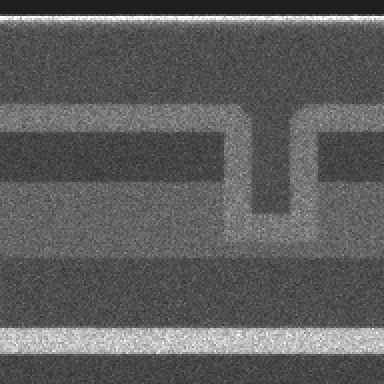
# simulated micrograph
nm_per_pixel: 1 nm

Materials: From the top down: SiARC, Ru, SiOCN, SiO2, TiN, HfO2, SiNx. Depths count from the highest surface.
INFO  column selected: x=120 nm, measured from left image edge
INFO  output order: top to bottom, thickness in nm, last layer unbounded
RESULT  SiARC 88, Ru 28, SiOCN 50, SiO2 76, TiN 70, HfO2 26, SiNx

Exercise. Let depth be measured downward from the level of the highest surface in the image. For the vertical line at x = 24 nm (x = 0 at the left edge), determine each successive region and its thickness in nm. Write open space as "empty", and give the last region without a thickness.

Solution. SiARC 88, Ru 28, SiOCN 50, SiO2 76, TiN 70, HfO2 26, SiNx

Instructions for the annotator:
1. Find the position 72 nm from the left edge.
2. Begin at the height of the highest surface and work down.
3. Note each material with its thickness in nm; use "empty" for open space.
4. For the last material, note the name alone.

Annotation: SiARC 88, Ru 28, SiOCN 50, SiO2 76, TiN 70, HfO2 26, SiNx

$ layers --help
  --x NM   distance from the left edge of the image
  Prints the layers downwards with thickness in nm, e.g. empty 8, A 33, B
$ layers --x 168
SiARC 88, Ru 28, SiOCN 50, SiO2 76, TiN 70, HfO2 26, SiNx